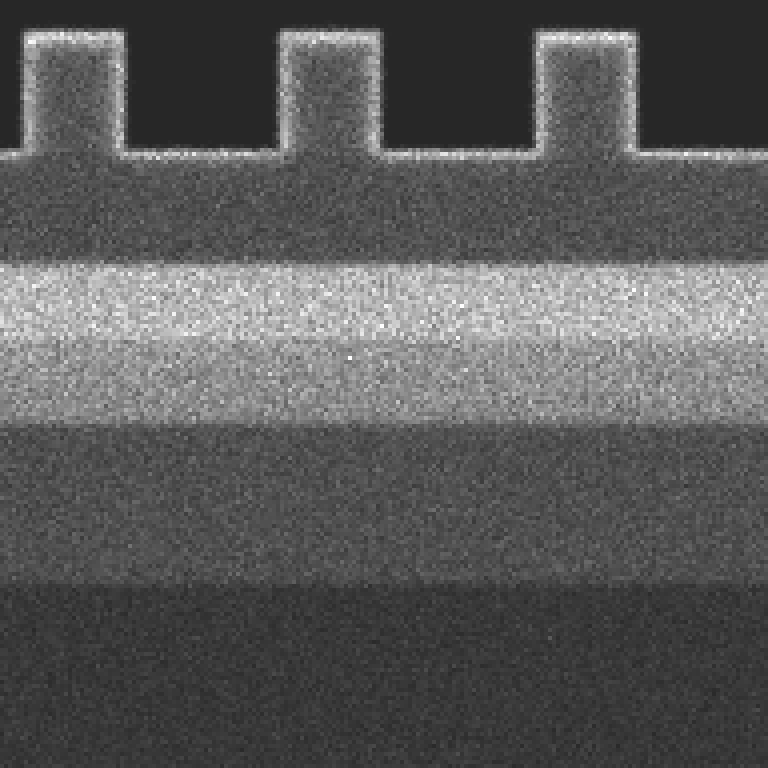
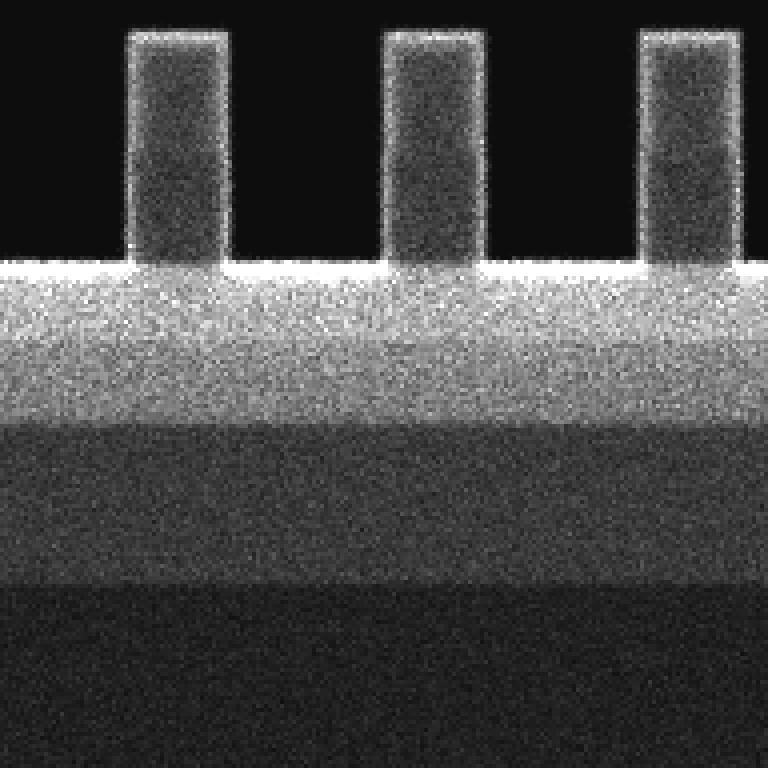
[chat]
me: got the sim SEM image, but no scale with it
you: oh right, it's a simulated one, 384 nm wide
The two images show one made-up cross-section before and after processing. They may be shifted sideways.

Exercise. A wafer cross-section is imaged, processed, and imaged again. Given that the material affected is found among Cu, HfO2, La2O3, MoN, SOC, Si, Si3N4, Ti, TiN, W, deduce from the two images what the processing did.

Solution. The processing removed TiN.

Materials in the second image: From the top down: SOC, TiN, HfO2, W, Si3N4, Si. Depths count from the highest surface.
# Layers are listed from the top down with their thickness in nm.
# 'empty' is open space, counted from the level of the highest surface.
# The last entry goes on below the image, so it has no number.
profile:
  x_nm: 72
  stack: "SOC 60, TiN 56, HfO2 38, W 42, Si3N4 80, Si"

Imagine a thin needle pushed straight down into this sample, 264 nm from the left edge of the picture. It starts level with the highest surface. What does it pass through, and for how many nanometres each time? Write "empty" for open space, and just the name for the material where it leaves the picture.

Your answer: empty 116, HfO2 38, W 42, Si3N4 80, Si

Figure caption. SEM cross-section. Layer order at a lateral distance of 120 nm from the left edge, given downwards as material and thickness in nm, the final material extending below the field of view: empty 116, HfO2 38, W 42, Si3N4 80, Si